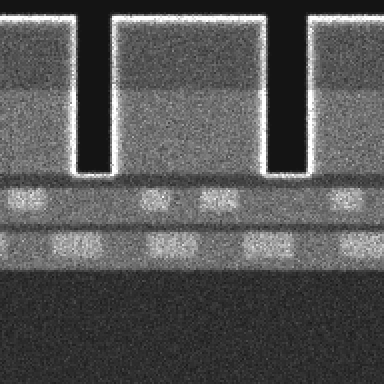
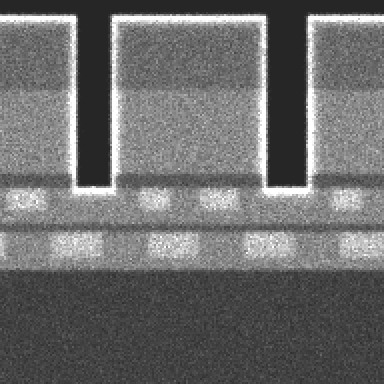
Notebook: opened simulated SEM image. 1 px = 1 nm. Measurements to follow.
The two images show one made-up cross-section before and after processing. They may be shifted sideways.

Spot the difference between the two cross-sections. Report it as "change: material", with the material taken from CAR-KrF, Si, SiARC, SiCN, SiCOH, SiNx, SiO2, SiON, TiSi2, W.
removed: SiCN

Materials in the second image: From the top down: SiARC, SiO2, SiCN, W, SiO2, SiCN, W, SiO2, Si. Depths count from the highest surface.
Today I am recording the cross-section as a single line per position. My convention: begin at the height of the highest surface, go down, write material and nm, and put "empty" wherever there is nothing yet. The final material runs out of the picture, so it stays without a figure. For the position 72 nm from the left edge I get SiARC 74, SiO2 84, SiCN 14, SiO2 36, SiCN 8, W 26, SiO2 12, Si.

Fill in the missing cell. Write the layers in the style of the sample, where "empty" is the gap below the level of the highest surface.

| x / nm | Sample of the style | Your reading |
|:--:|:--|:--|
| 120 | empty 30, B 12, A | SiARC 74, SiO2 84, SiCN 14, SiO2 36, SiCN 8, SiO2 38, Si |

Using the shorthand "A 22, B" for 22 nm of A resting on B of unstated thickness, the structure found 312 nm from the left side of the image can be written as SiARC 74, SiO2 84, SiCN 14, SiO2 36, SiCN 8, SiO2 38, Si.